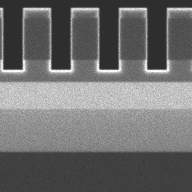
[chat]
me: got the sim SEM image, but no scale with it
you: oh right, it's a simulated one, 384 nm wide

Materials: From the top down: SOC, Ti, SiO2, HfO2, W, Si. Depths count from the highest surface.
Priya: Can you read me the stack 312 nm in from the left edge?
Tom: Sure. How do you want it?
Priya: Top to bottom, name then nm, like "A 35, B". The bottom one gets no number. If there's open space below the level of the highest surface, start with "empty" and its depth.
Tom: empty 124, SiO2 24, HfO2 54, W 86, Si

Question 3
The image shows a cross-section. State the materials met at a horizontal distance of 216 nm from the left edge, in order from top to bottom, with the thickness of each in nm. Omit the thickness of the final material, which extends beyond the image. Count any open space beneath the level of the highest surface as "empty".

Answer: empty 124, SiO2 24, HfO2 54, W 86, Si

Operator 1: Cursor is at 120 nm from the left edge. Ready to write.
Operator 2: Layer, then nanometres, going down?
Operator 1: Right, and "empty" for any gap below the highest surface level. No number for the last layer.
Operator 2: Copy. empty 124, SiO2 24, HfO2 54, W 86, Si